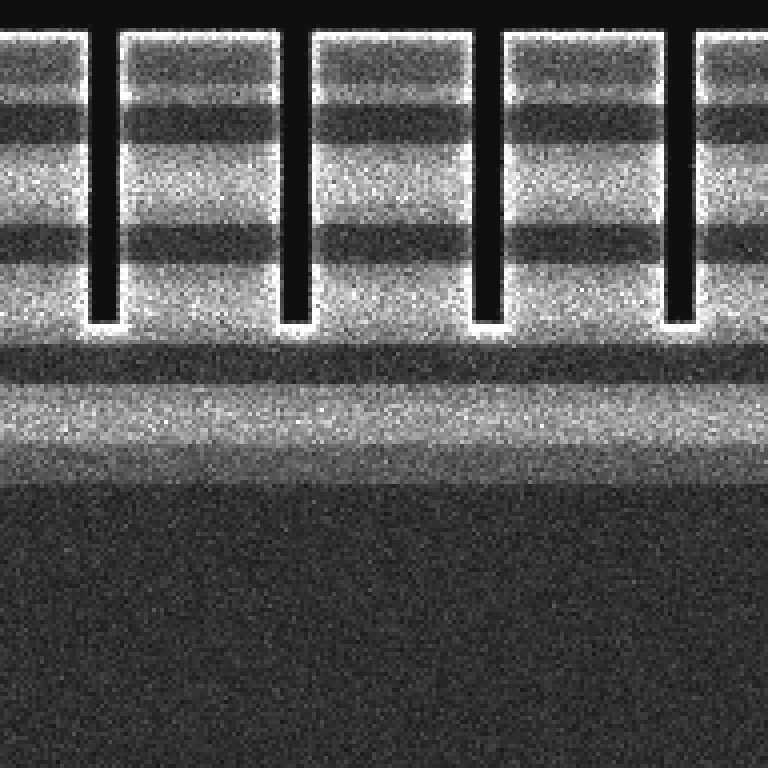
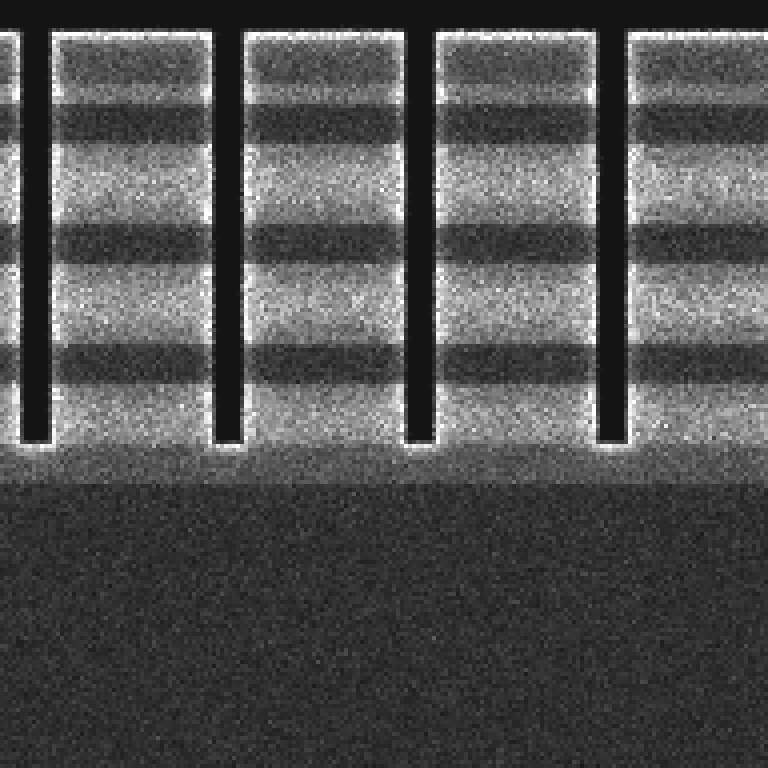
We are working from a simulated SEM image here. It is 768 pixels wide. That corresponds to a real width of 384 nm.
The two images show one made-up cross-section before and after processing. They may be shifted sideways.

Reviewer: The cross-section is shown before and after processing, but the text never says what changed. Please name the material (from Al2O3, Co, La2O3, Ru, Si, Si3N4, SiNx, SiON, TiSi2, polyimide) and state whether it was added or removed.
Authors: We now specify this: Al2O3 and Co and Si, removed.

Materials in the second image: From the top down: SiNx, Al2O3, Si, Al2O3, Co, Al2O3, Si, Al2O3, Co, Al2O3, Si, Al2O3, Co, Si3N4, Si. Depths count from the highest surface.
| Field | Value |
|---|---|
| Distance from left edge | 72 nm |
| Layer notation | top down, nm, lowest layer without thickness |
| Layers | SiNx 26, Al2O3 10, Si 20, Al2O3 10, Co 20, Al2O3 10, Si 20, Al2O3 10, Co 20, Al2O3 10, Si 20, Al2O3 10, Co 20, Si3N4 20, Si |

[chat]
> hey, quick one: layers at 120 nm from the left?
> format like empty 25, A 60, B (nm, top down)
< empty 206, Si3N4 20, Si